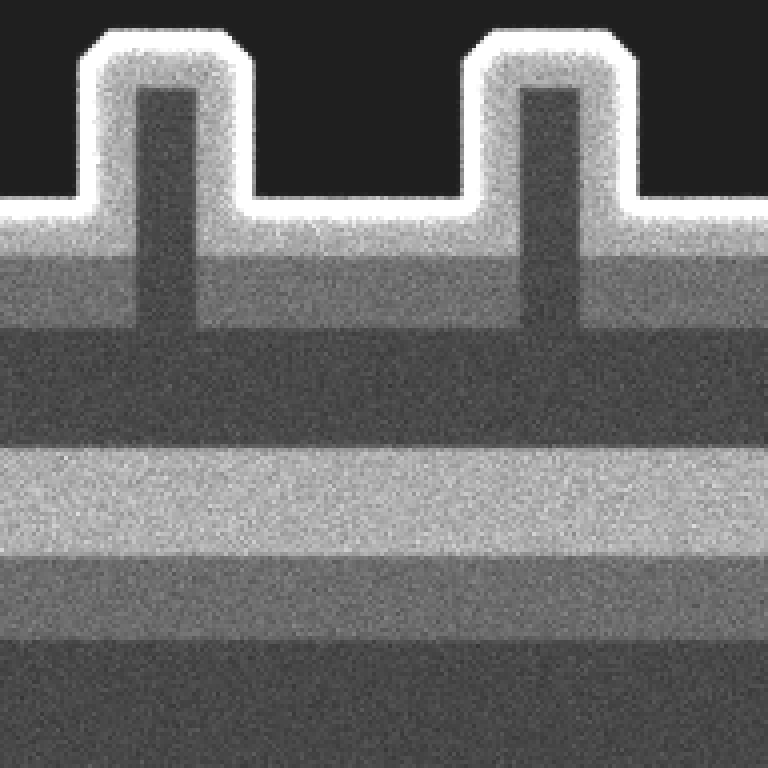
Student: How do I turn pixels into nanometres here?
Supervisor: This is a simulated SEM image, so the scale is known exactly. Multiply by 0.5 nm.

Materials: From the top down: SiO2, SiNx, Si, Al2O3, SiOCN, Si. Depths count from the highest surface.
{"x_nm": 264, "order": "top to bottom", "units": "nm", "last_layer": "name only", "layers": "SiO2 28, Si 180, Al2O3 54, SiOCN 42, Si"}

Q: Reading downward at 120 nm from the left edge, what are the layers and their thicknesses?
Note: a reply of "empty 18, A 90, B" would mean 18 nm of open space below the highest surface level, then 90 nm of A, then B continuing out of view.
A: empty 10, SiO2 102, SiNx 36, Si 60, Al2O3 54, SiOCN 42, Si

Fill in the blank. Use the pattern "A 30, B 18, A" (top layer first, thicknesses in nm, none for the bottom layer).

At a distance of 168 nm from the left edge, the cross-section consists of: empty 84, SiO2 28, SiNx 36, Si 60, Al2O3 54, SiOCN 42, Si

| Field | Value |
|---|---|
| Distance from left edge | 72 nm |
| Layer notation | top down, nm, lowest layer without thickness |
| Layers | SiO2 28, Si 180, Al2O3 54, SiOCN 42, Si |